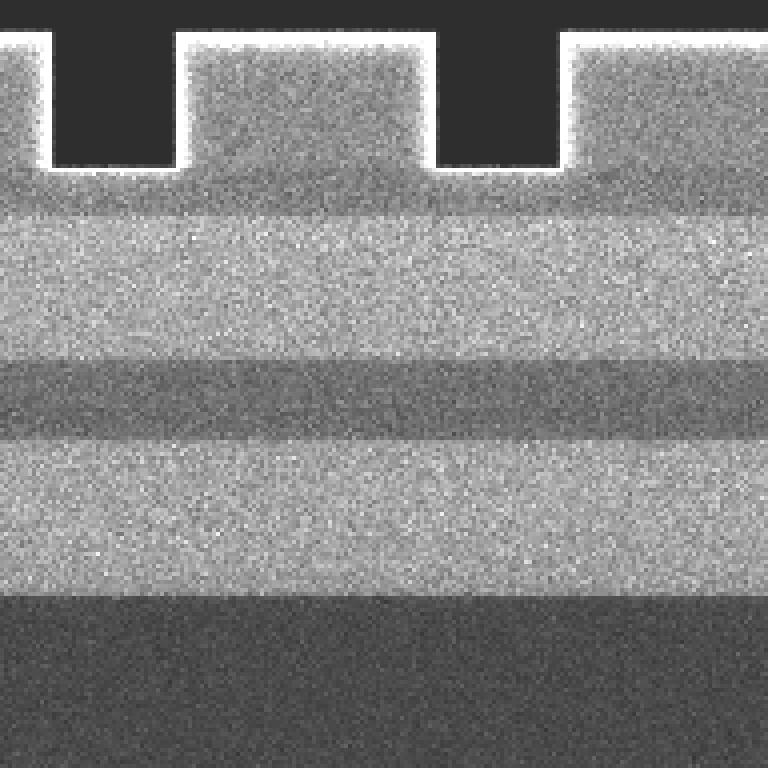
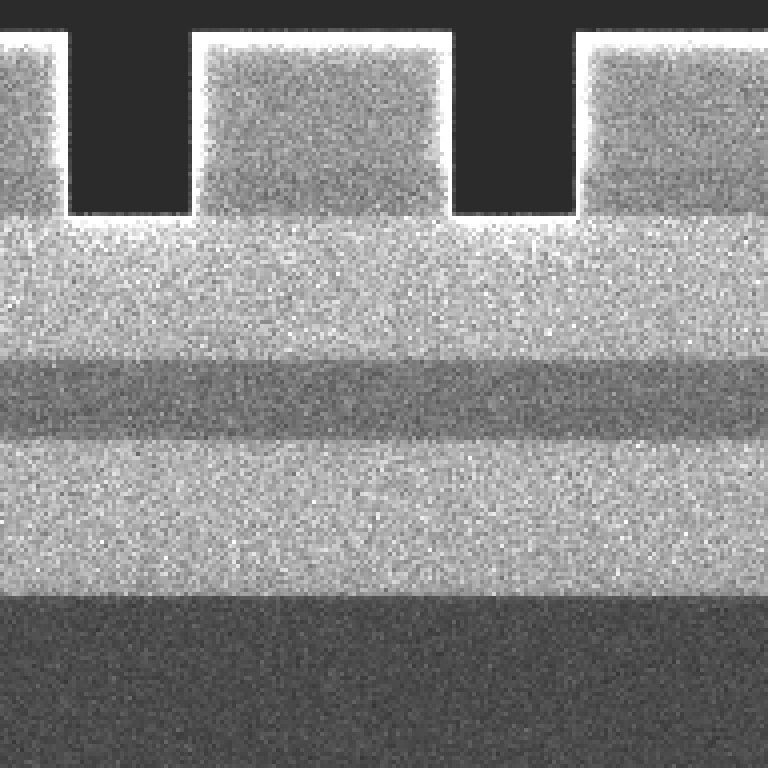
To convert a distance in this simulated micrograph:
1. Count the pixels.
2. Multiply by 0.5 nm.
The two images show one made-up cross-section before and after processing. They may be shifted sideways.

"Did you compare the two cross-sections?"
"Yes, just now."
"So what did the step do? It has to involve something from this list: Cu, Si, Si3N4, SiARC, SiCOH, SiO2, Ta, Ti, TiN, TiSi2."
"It removed TiN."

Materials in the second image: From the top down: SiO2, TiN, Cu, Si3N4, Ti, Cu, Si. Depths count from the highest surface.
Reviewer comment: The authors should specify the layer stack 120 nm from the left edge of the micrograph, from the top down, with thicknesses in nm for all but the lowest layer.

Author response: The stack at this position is SiO2 68, TiN 24, Cu 72, Si3N4 24, Ti 16, Cu 78, Si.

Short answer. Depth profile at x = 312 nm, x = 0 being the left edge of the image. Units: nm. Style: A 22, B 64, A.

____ SiO2 68, TiN 24, Cu 72, Si3N4 24, Ti 16, Cu 78, Si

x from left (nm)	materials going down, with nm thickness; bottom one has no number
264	empty 92, Cu 72, Si3N4 24, Ti 16, Cu 78, Si